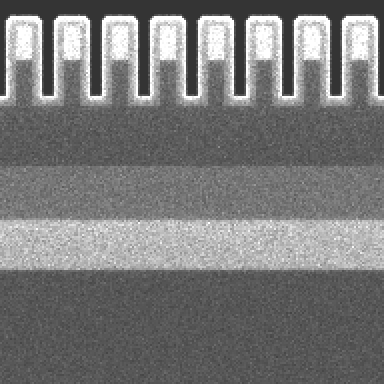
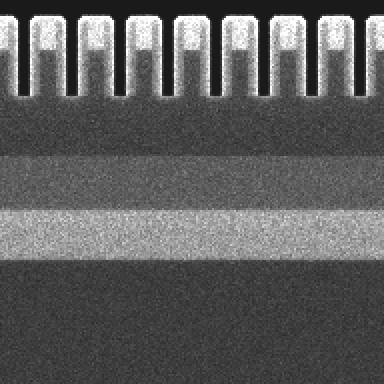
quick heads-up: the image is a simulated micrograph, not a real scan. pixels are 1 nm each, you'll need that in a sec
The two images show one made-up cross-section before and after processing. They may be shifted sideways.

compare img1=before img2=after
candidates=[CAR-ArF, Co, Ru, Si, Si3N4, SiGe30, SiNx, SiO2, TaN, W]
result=removed:Si3N4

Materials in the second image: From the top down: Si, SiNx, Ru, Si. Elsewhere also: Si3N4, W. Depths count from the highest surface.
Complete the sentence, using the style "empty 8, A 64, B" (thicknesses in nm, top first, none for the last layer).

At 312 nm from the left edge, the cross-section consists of empty 80, Si 60, SiNx 54, Ru 50, Si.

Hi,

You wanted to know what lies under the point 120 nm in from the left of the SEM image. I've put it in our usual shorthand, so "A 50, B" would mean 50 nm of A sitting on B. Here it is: empty 80, Si 60, SiNx 54, Ru 50, Si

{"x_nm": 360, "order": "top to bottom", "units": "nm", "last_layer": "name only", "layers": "empty 80, Si 60, SiNx 54, Ru 50, Si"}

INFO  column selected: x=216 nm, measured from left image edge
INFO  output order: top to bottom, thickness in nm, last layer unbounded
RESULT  empty 80, Si 60, SiNx 54, Ru 50, Si